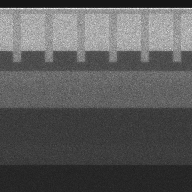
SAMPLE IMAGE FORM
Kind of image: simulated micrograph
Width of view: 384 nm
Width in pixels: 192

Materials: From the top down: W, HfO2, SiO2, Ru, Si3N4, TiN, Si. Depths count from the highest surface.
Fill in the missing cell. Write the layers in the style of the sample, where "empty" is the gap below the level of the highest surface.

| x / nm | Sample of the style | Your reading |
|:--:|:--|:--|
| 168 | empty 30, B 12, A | W 108, SiO2 18, Ru 74, Si3N4 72, TiN 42, Si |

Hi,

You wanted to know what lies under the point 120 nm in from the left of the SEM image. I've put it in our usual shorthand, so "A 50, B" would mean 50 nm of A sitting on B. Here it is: W 12, HfO2 74, SiO2 40, Ru 74, Si3N4 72, TiN 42, Si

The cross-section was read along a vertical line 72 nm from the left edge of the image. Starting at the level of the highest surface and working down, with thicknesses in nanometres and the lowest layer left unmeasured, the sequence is W 12, HfO2 74, SiO2 40, Ru 74, Si3N4 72, TiN 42, Si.